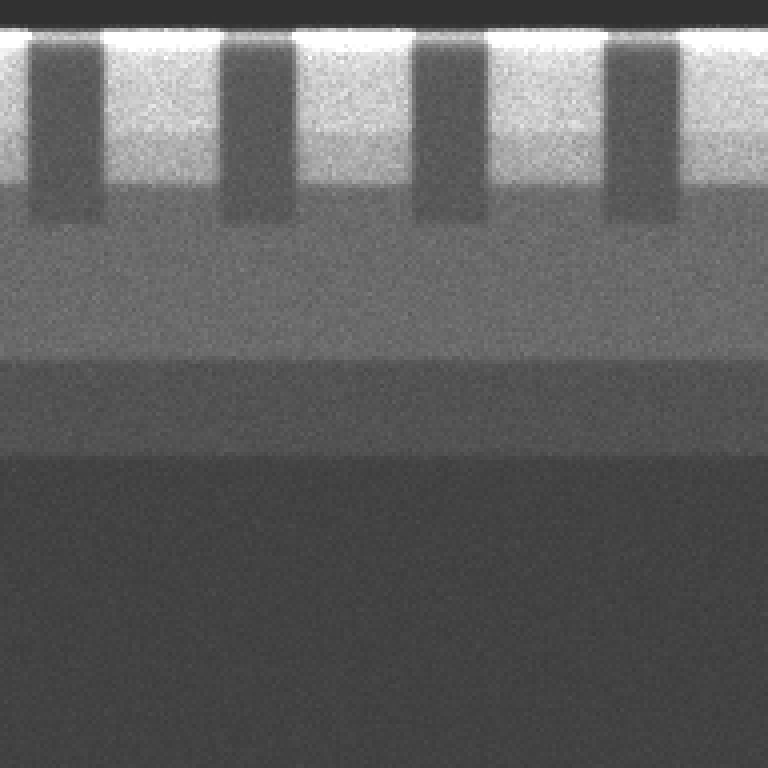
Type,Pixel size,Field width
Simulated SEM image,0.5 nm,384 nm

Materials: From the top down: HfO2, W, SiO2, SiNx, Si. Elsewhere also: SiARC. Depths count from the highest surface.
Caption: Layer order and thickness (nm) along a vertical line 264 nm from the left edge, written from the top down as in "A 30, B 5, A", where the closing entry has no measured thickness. HfO2 50, W 26, SiO2 88, SiNx 48, Si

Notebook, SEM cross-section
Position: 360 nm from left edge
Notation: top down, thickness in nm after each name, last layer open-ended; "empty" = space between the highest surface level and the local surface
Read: HfO2 50, W 26, SiO2 88, SiNx 48, Si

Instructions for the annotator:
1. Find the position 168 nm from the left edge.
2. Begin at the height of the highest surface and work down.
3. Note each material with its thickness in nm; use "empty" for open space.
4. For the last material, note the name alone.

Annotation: HfO2 50, W 26, SiO2 88, SiNx 48, Si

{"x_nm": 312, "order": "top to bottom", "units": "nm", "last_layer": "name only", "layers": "SiARC 96, SiO2 68, SiNx 48, Si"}